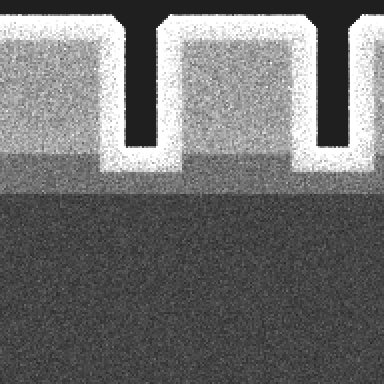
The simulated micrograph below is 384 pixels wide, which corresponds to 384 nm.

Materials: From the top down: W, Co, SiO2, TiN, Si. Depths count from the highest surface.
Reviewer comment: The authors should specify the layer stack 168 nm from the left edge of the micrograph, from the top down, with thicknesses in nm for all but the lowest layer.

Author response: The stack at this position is empty 2, W 154, TiN 22, Si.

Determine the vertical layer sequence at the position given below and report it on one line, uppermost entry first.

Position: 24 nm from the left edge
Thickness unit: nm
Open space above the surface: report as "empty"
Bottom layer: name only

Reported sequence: W 24, Co 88, SiO2 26, TiN 40, Si